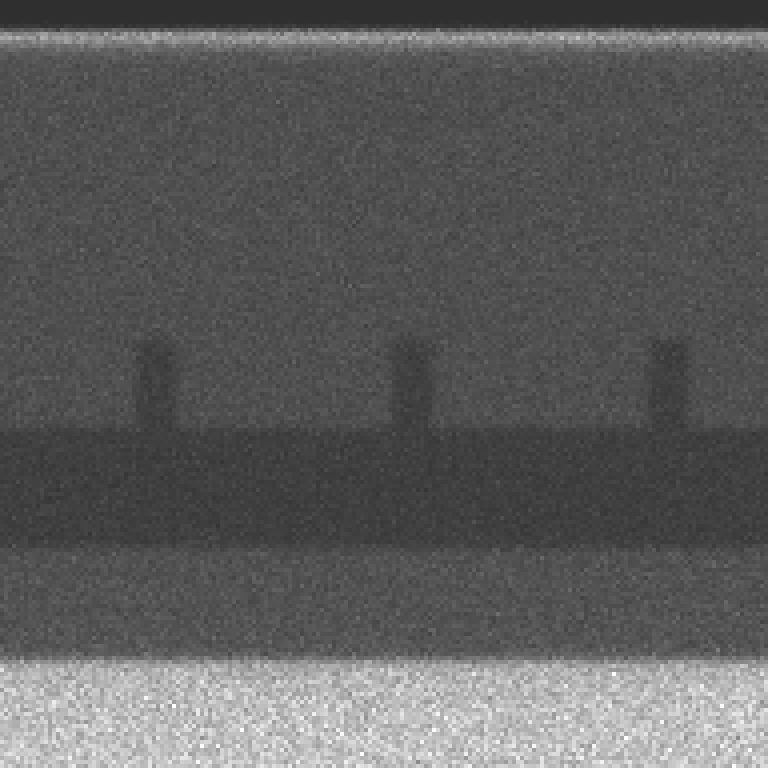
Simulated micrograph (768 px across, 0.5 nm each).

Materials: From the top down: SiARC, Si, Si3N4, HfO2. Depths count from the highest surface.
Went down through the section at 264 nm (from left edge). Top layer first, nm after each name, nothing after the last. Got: SiARC 198, Si 60, Si3N4 56, HfO2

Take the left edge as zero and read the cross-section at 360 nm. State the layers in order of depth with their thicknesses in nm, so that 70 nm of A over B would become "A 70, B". SiARC 198, Si 60, Si3N4 56, HfO2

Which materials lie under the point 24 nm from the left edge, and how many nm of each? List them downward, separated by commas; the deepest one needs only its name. SiARC 198, Si 60, Si3N4 56, HfO2